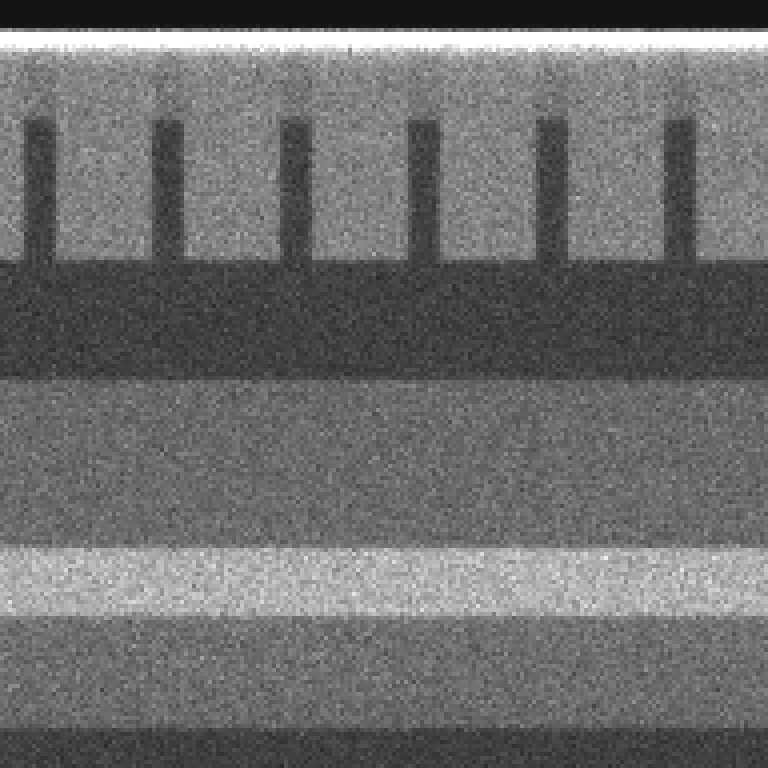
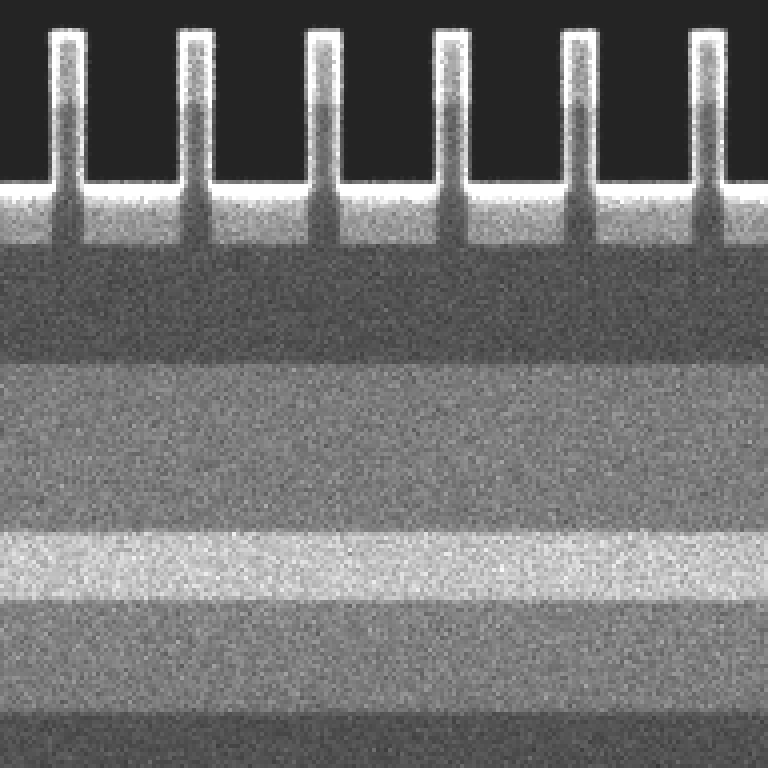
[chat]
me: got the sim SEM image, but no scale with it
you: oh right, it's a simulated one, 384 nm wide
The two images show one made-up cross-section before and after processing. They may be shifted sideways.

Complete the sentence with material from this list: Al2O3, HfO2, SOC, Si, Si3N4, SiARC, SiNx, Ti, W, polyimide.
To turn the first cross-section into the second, SOC must be removed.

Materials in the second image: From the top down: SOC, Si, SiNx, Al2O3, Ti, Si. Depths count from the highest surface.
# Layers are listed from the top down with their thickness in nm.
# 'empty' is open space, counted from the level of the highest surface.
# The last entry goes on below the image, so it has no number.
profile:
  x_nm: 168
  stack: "Ti 36, Si 130, SiNx 84, Al2O3 34, Ti 56, Si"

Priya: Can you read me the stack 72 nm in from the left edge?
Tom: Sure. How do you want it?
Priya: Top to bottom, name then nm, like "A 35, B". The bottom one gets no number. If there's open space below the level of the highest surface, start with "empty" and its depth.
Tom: empty 76, SOC 30, Si 60, SiNx 84, Al2O3 34, Ti 56, Si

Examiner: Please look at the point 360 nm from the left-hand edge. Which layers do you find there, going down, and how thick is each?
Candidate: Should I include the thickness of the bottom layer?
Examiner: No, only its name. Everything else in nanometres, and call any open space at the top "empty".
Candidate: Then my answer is Ti 36, Si 130, SiNx 84, Al2O3 34, Ti 56, Si